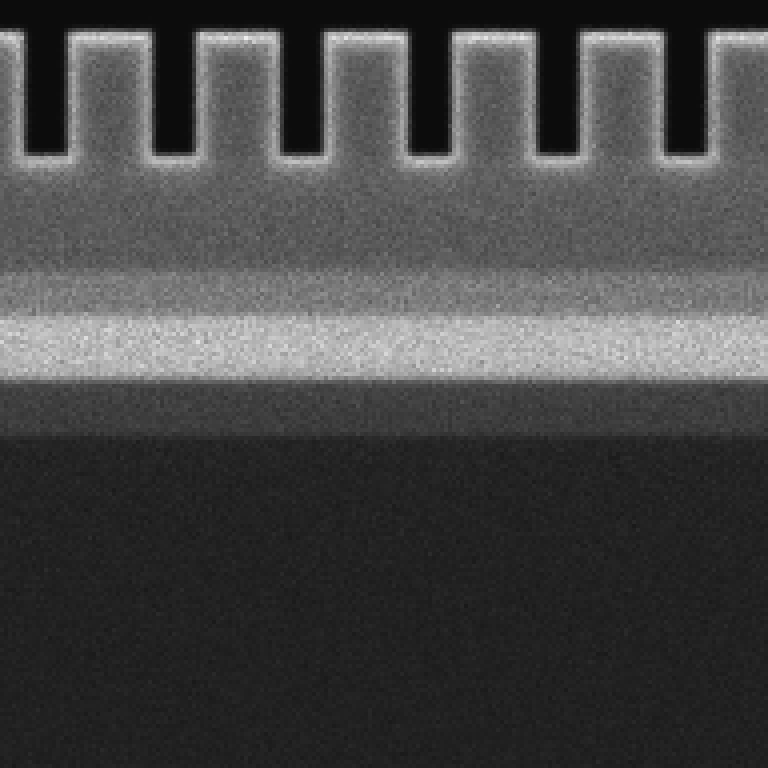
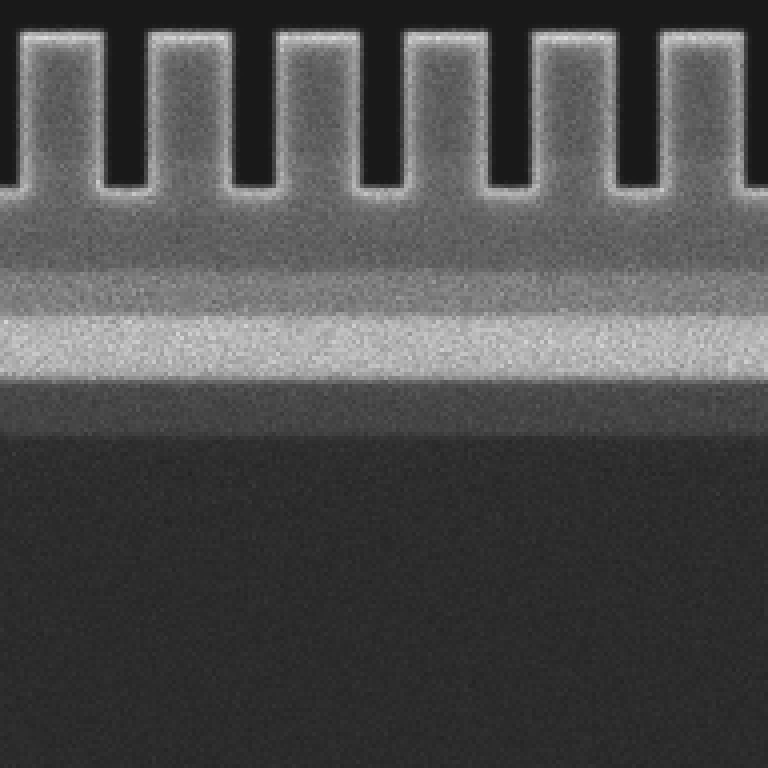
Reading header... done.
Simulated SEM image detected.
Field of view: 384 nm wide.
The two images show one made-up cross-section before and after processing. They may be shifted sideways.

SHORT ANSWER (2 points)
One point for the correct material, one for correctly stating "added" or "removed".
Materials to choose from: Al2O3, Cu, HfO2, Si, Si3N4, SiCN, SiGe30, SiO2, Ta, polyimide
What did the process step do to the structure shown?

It removed Al2O3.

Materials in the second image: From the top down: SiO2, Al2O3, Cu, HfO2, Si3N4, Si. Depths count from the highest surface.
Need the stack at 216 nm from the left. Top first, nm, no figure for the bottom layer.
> SiO2 62, Al2O3 58, Cu 22, HfO2 32, Si3N4 28, Si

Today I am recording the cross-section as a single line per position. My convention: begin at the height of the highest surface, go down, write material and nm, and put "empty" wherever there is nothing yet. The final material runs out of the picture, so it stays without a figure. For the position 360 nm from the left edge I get SiO2 62, Al2O3 58, Cu 22, HfO2 32, Si3N4 28, Si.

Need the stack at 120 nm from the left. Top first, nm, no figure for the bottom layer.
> empty 78, Al2O3 42, Cu 22, HfO2 32, Si3N4 28, Si